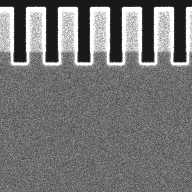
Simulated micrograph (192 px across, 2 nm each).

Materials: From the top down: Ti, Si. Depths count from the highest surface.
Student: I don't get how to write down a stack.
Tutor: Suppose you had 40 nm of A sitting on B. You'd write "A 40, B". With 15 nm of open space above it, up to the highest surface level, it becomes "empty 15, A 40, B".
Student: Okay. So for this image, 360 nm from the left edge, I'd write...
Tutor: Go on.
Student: empty 110, Si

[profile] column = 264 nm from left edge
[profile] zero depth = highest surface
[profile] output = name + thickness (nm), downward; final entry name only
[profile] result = Ti 88, Si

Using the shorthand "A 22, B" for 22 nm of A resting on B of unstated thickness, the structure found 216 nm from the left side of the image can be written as Ti 88, Si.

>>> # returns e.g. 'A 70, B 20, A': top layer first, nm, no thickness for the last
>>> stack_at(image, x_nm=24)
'Ti 88, Si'